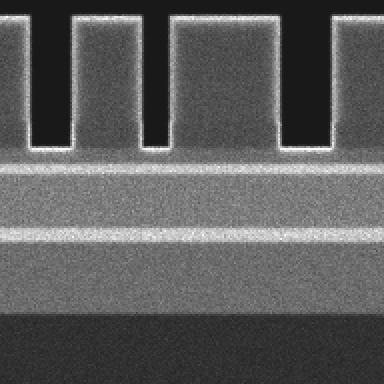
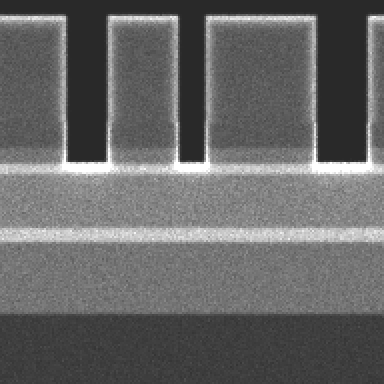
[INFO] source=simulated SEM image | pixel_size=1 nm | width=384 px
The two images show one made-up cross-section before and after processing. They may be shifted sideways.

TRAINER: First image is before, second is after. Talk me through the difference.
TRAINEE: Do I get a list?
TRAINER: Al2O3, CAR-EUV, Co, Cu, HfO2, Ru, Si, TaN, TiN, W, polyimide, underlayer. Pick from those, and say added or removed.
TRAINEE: removed: Co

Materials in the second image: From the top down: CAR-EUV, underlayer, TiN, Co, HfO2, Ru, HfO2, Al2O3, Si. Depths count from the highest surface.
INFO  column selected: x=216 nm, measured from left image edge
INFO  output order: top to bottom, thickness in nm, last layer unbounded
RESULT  CAR-EUV 64, underlayer 42, TiN 26, Co 16, HfO2 10, Ru 54, HfO2 14, Al2O3 72, Si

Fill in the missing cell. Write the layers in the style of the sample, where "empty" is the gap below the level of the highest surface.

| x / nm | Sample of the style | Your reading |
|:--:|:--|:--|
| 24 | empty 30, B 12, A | CAR-EUV 64, underlayer 42, TiN 26, Co 16, HfO2 10, Ru 54, HfO2 14, Al2O3 72, Si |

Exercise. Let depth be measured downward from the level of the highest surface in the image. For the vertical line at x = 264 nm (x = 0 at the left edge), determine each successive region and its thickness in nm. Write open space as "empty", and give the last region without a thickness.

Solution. CAR-EUV 64, underlayer 42, TiN 26, Co 16, HfO2 10, Ru 54, HfO2 14, Al2O3 72, Si